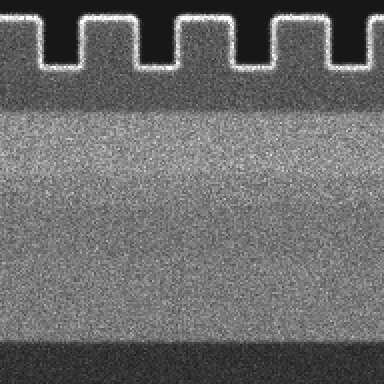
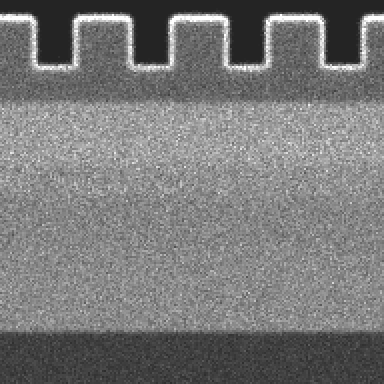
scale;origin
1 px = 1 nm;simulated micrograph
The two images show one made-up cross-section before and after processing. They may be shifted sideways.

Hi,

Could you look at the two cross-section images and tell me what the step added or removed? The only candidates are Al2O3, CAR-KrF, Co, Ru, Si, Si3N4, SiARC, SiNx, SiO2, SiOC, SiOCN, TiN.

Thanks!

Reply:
removed SiNx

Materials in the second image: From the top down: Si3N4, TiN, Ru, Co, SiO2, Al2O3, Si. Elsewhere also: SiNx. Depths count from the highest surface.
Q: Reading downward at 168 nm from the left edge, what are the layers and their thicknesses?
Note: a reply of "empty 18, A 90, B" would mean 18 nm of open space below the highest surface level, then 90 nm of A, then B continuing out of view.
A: empty 50, TiN 36, Ru 62, Co 32, SiO2 52, Al2O3 84, Si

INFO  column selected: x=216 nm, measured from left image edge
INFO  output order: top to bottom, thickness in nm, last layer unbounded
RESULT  Si3N4 50, TiN 36, Ru 62, Co 32, SiO2 52, Al2O3 84, Si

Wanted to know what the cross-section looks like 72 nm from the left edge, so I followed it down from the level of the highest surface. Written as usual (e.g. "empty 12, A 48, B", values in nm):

empty 50, TiN 36, Ru 62, Co 32, SiO2 52, Al2O3 84, Si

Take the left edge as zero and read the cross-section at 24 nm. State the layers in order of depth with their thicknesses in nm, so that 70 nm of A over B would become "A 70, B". Si3N4 50, TiN 36, Ru 62, Co 32, SiO2 52, Al2O3 84, Si